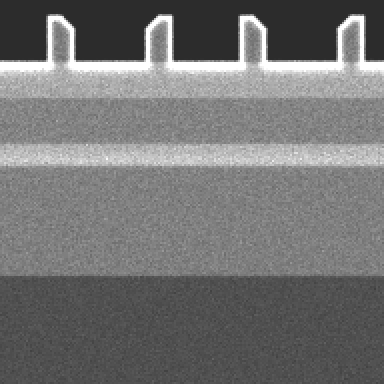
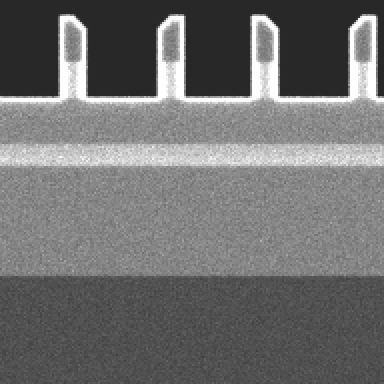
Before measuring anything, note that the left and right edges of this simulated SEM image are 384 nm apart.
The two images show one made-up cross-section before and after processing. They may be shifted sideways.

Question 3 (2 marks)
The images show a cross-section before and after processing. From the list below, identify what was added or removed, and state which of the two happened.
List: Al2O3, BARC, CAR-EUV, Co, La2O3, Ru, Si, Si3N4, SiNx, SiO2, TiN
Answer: SiO2 was removed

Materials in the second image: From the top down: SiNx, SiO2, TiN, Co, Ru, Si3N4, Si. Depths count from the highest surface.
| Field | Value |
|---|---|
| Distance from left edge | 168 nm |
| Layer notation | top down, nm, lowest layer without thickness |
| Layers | empty 2, SiNx 44, SiO2 36, TiN 46, Co 12, Ru 10, Si3N4 110, Si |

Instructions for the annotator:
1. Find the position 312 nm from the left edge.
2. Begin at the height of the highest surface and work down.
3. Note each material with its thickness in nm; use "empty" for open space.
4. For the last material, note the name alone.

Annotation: empty 82, TiN 46, Co 12, Ru 10, Si3N4 110, Si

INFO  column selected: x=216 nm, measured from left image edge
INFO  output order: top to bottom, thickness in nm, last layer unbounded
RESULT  empty 82, TiN 46, Co 12, Ru 10, Si3N4 110, Si